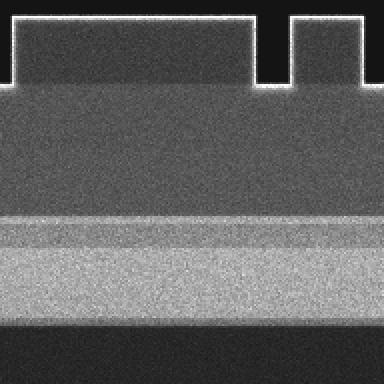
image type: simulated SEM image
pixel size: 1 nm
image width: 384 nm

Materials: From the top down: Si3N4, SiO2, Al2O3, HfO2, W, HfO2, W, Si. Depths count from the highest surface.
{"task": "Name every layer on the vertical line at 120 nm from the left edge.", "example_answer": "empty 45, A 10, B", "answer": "Si3N4 68, SiO2 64, Al2O3 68, HfO2 8, W 24, HfO2 70, W 8, Si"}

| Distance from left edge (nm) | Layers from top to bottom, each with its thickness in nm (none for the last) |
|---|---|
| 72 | Si3N4 68, SiO2 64, Al2O3 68, HfO2 8, W 24, HfO2 70, W 8, Si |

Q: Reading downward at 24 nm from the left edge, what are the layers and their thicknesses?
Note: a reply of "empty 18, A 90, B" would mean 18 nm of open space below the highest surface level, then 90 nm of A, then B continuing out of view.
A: Si3N4 68, SiO2 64, Al2O3 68, HfO2 8, W 24, HfO2 70, W 8, Si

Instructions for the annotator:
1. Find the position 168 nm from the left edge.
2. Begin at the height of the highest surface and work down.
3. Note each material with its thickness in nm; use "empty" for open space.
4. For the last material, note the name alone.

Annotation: Si3N4 68, SiO2 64, Al2O3 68, HfO2 8, W 24, HfO2 70, W 8, Si